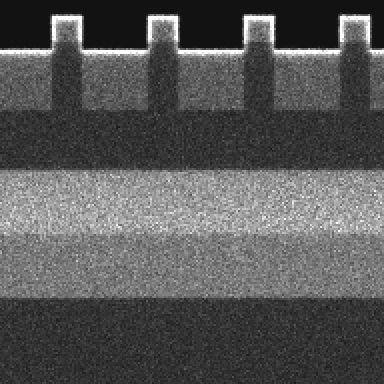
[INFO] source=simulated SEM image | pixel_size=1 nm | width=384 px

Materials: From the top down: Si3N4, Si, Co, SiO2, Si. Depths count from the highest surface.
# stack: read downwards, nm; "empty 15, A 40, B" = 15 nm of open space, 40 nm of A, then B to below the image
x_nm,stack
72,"Si3N4 26, Si 128, Co 64, SiO2 64, Si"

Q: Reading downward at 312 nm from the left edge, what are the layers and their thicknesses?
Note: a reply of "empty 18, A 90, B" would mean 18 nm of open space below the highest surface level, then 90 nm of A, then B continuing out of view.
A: empty 34, Si3N4 60, Si 60, Co 64, SiO2 64, Si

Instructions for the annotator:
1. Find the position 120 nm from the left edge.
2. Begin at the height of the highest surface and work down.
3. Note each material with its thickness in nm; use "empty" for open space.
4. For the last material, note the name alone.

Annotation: empty 34, Si3N4 60, Si 60, Co 64, SiO2 64, Si